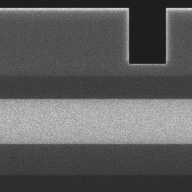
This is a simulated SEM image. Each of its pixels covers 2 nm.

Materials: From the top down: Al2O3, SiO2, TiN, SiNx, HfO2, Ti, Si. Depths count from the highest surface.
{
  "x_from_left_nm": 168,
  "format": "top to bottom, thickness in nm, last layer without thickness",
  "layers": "Al2O3 24, SiO2 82, TiN 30, SiNx 46, HfO2 90, Ti 62, Si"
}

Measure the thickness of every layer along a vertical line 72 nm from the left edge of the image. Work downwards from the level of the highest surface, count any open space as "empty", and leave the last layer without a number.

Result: Al2O3 24, SiO2 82, TiN 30, SiNx 46, HfO2 90, Ti 62, Si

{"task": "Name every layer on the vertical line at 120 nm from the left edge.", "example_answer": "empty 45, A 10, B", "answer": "Al2O3 24, SiO2 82, TiN 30, SiNx 46, HfO2 90, Ti 62, Si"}